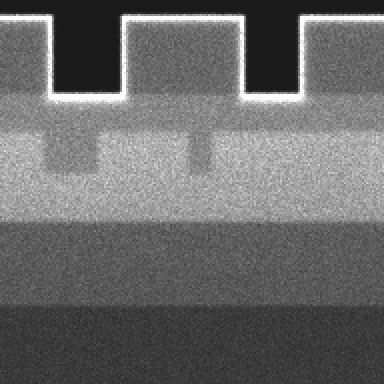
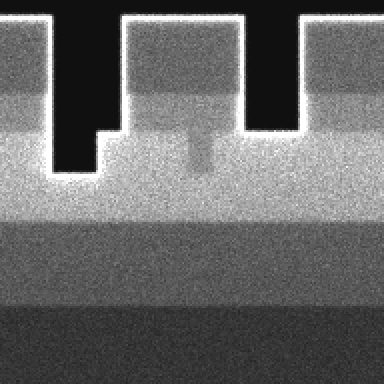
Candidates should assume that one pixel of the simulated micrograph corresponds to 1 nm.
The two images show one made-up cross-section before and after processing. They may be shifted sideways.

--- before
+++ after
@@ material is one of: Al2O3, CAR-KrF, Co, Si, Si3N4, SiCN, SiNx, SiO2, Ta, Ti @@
SiO2 removed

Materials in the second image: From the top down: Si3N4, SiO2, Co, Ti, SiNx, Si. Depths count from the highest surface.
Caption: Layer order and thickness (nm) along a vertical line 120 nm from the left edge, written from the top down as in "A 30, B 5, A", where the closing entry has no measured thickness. empty 116, Co 90, Ti 52, SiNx 32, Si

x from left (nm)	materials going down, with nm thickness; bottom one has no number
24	Si3N4 78, SiO2 38, Co 90, Ti 52, SiNx 32, Si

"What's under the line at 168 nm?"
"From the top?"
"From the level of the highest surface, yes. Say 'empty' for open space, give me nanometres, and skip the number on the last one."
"Si3N4 78, SiO2 38, Co 90, Ti 52, SiNx 32, Si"